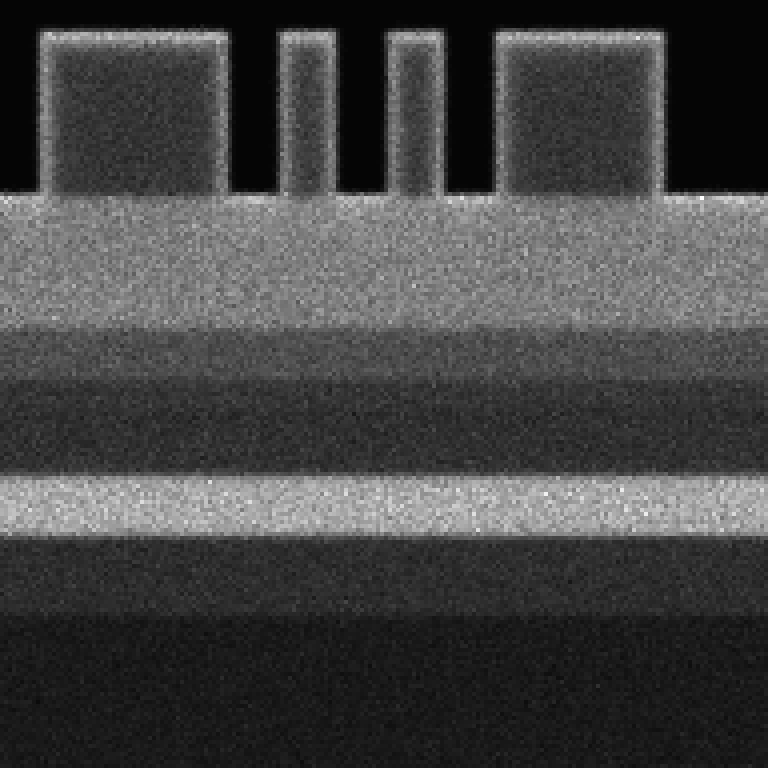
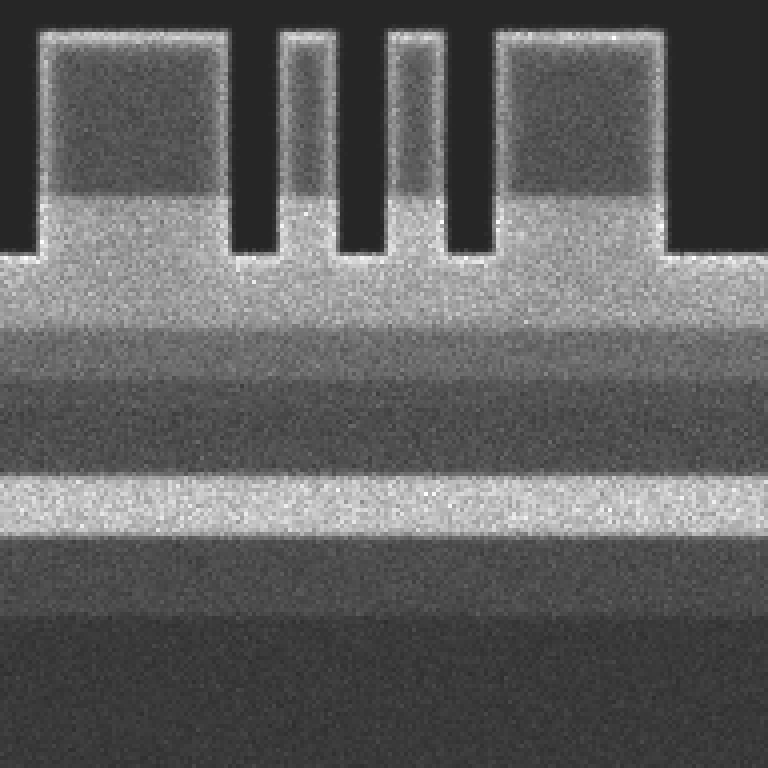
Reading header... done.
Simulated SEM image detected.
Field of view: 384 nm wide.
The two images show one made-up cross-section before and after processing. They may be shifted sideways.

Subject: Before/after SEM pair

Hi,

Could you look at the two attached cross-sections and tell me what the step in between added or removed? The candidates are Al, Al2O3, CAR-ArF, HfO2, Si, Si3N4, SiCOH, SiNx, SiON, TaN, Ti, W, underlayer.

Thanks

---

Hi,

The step removed W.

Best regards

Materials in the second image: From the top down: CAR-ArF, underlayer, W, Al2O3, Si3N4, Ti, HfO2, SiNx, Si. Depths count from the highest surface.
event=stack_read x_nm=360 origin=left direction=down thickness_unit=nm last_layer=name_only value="empty 112, W 36, Al2O3 26, Si3N4 14, Ti 34, HfO2 30, SiNx 40, Si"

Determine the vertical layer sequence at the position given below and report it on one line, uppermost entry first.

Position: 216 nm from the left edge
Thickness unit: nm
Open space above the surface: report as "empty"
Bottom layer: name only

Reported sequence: CAR-ArF 42, underlayer 40, W 66, Al2O3 26, Si3N4 14, Ti 34, HfO2 30, SiNx 40, Si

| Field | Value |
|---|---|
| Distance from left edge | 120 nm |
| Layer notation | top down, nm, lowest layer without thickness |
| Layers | empty 112, W 36, Al2O3 26, Si3N4 14, Ti 34, HfO2 30, SiNx 40, Si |